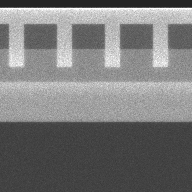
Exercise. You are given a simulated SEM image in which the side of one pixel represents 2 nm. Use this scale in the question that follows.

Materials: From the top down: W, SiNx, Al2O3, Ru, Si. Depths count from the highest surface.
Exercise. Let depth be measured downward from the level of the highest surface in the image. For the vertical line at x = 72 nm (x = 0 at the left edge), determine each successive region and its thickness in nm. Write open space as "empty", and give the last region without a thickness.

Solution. W 32, SiNx 50, Al2O3 66, Ru 80, Si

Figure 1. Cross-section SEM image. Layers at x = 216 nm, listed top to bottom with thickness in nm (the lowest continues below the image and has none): W 118, Al2O3 30, Ru 80, Si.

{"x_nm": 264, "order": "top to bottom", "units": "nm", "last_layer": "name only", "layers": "W 32, SiNx 50, Al2O3 66, Ru 80, Si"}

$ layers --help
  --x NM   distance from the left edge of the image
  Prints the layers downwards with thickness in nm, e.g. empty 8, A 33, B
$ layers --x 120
W 118, Al2O3 30, Ru 80, Si